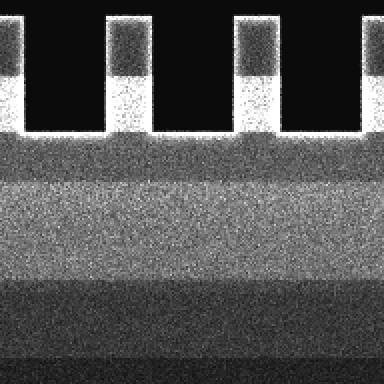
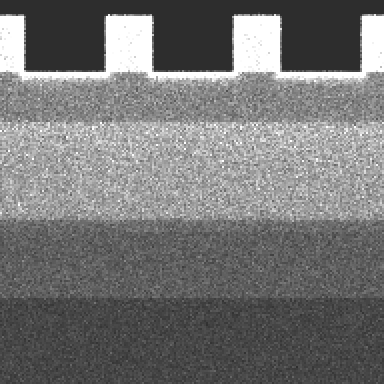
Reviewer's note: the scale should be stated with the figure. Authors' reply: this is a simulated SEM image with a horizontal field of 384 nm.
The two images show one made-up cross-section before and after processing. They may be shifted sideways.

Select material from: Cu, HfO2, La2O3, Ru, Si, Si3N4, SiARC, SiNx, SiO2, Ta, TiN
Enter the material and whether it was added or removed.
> SiARC / removed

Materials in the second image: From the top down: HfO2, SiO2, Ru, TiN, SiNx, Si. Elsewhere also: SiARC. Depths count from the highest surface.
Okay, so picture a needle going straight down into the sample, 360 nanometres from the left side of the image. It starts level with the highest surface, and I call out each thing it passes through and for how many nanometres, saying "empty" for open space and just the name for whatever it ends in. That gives empty 56, SiO2 50, Ru 98, TiN 12, SiNx 66, Si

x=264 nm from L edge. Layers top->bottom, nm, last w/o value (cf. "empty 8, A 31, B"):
HfO2 56, SiO2 50, Ru 98, TiN 12, SiNx 66, Si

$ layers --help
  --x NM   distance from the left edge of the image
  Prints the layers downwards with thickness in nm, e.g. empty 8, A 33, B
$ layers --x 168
empty 56, SiO2 50, Ru 98, TiN 12, SiNx 66, Si